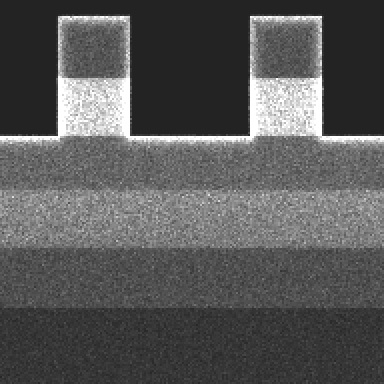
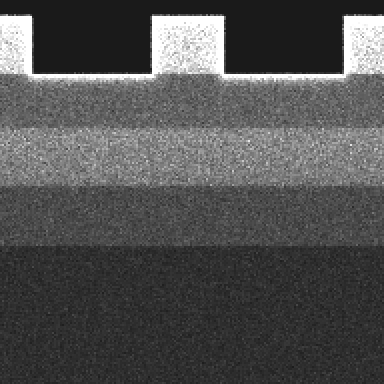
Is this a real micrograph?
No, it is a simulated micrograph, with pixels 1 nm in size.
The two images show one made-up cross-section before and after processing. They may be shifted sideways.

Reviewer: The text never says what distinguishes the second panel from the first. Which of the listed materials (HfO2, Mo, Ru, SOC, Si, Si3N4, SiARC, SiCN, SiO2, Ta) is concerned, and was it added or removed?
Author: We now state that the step removed SOC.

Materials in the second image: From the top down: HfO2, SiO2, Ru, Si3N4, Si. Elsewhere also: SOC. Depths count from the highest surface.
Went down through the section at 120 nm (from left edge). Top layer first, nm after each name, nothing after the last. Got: empty 58, SiO2 54, Ru 58, Si3N4 60, Si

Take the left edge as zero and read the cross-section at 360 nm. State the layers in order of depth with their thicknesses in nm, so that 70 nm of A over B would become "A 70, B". HfO2 58, SiO2 54, Ru 58, Si3N4 60, Si